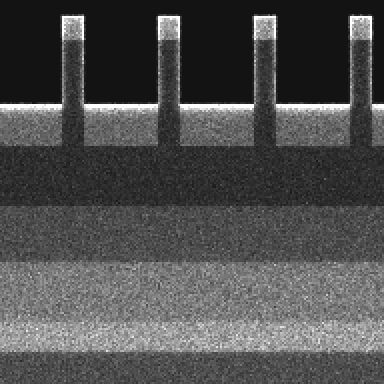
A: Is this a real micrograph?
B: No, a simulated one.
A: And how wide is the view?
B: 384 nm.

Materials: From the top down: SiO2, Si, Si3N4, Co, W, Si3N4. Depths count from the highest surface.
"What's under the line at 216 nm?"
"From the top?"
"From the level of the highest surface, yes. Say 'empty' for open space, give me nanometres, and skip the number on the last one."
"empty 88, SiO2 42, Si 60, Si3N4 56, Co 60, W 30, Si3N4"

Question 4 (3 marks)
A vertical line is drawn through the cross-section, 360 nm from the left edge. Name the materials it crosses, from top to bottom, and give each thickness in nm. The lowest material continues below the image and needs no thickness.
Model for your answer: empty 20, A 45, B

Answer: Co 24, Si 166, Si3N4 56, Co 60, W 30, Si3N4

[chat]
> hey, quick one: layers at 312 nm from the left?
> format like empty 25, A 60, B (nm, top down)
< empty 88, SiO2 42, Si 60, Si3N4 56, Co 60, W 30, Si3N4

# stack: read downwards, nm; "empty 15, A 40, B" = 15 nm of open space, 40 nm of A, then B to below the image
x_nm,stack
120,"empty 88, SiO2 42, Si 60, Si3N4 56, Co 60, W 30, Si3N4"